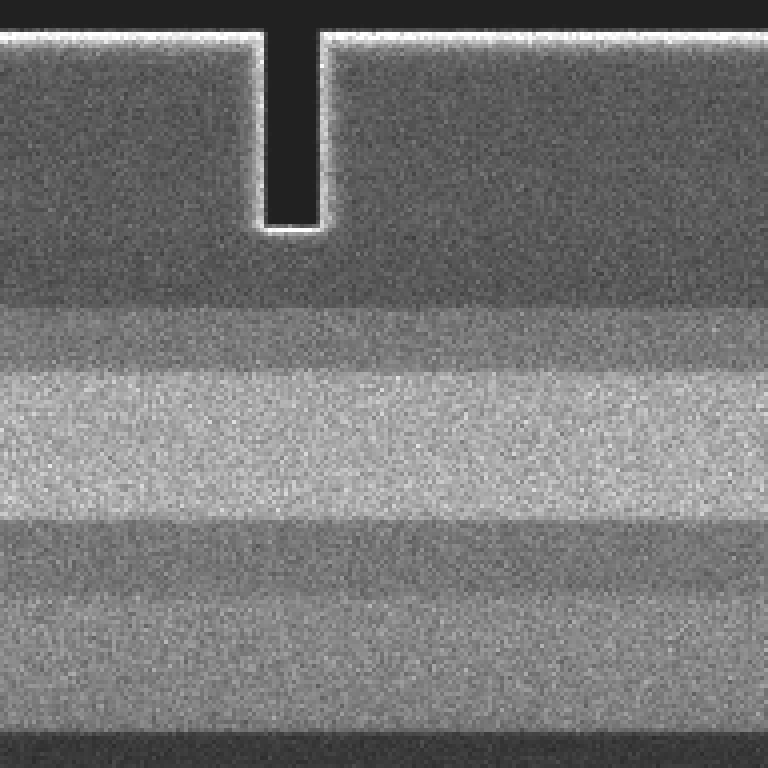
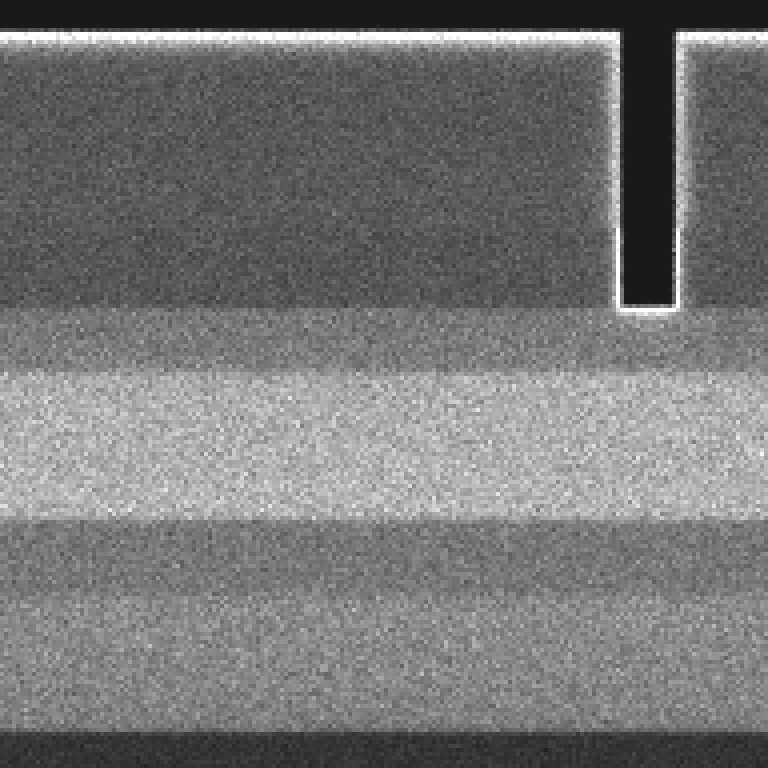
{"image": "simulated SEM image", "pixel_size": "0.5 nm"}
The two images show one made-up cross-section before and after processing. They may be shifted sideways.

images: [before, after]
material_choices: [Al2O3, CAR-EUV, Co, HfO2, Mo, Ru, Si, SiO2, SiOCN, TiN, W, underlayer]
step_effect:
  removed: TiN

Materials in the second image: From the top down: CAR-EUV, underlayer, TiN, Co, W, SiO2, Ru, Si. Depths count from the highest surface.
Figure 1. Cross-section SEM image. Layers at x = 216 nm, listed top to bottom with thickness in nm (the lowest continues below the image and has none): CAR-EUV 64, underlayer 34, TiN 40, Co 32, W 74, SiO2 38, Ru 68, Si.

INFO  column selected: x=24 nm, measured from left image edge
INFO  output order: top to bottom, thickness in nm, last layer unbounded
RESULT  CAR-EUV 64, underlayer 34, TiN 40, Co 32, W 74, SiO2 38, Ru 68, Si